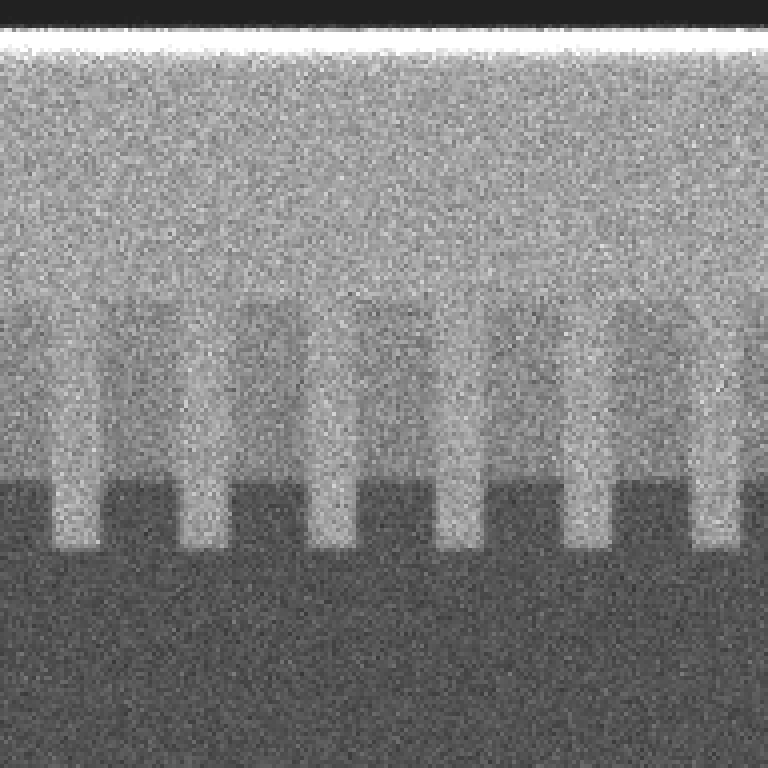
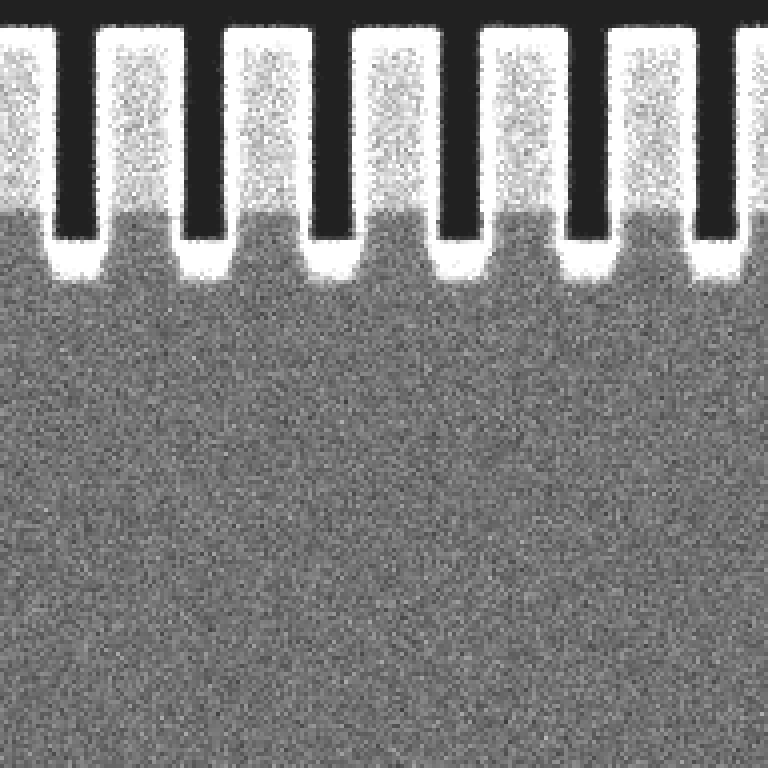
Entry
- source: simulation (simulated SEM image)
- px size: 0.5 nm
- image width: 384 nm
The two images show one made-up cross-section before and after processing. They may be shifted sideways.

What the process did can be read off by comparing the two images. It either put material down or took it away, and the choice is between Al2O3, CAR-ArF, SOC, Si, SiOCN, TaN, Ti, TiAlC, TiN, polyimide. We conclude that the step removed SOC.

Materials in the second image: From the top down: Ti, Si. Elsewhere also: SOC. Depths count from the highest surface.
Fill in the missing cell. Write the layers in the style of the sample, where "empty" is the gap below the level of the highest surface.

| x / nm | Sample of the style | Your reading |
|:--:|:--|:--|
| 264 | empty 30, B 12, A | Ti 90, Si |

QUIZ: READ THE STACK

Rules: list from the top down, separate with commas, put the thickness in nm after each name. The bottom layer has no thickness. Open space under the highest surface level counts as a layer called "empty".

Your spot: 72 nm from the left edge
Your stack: Ti 90, Si